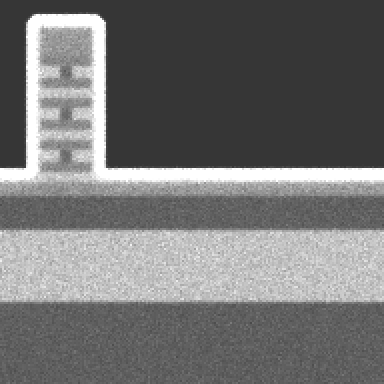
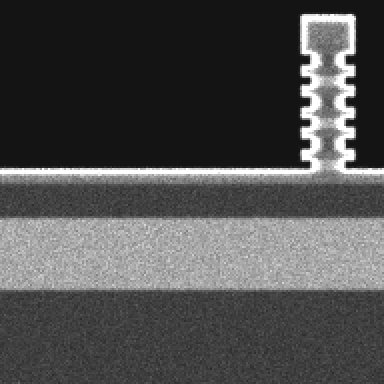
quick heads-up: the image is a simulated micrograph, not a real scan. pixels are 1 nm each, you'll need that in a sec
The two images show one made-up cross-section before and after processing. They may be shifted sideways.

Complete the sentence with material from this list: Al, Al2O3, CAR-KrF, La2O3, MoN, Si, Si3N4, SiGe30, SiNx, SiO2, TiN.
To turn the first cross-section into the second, Al2O3 must be removed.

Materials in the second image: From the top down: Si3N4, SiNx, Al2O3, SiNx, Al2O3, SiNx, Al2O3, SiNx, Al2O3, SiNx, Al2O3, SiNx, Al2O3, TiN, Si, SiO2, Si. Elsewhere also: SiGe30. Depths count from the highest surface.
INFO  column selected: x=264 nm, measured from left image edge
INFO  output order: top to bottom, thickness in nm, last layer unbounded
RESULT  empty 154, TiN 14, Si 34, SiO2 72, Si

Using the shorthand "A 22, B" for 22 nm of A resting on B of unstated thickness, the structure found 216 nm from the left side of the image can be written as empty 154, TiN 14, Si 34, SiO2 72, Si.